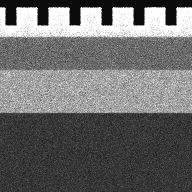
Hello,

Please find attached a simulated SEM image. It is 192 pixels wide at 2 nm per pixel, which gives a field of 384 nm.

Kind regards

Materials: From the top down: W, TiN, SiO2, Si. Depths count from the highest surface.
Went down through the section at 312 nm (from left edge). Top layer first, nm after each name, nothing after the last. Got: W 58, TiN 66, SiO2 86, Si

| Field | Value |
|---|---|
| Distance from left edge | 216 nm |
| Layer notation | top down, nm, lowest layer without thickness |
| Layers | empty 36, W 22, TiN 66, SiO2 86, Si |